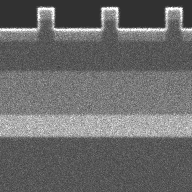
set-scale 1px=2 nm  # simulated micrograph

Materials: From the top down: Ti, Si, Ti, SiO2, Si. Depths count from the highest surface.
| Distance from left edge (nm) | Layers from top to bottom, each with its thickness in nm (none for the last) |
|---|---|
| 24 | empty 42, Ti 24, Si 60, Ti 88, SiO2 44, Si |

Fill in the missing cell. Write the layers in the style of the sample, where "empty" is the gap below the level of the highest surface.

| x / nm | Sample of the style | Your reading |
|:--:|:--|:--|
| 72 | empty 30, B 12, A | empty 42, Ti 24, Si 60, Ti 88, SiO2 44, Si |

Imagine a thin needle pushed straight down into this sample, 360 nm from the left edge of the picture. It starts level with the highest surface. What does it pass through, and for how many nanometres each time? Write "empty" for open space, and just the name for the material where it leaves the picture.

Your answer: Ti 24, Si 102, Ti 88, SiO2 44, Si